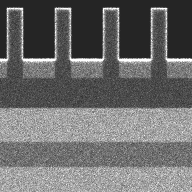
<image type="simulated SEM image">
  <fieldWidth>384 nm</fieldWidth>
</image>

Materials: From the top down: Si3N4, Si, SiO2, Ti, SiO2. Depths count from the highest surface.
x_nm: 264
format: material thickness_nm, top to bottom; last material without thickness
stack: empty 102, Si3N4 38, Si 60, SiO2 68, Ti 50, SiO2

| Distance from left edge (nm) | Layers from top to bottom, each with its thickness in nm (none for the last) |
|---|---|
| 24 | Si 200, SiO2 68, Ti 50, SiO2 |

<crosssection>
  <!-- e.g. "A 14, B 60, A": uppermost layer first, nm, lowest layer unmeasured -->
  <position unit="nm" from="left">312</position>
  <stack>Si 200, SiO2 68, Ti 50, SiO2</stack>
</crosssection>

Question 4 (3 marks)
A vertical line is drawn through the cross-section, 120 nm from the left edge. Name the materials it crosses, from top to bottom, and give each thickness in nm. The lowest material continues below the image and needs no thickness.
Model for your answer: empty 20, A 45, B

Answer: Si 200, SiO2 68, Ti 50, SiO2